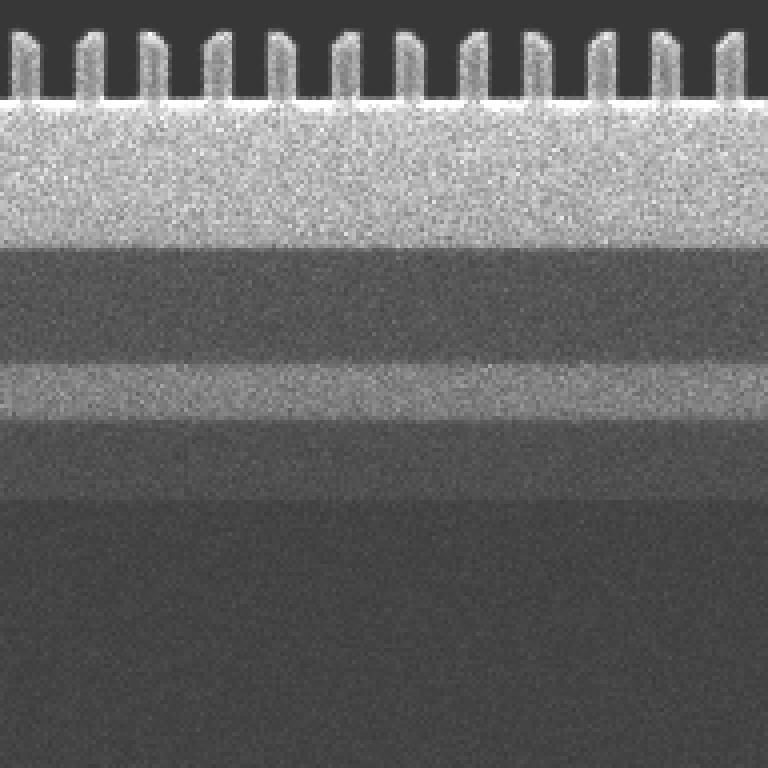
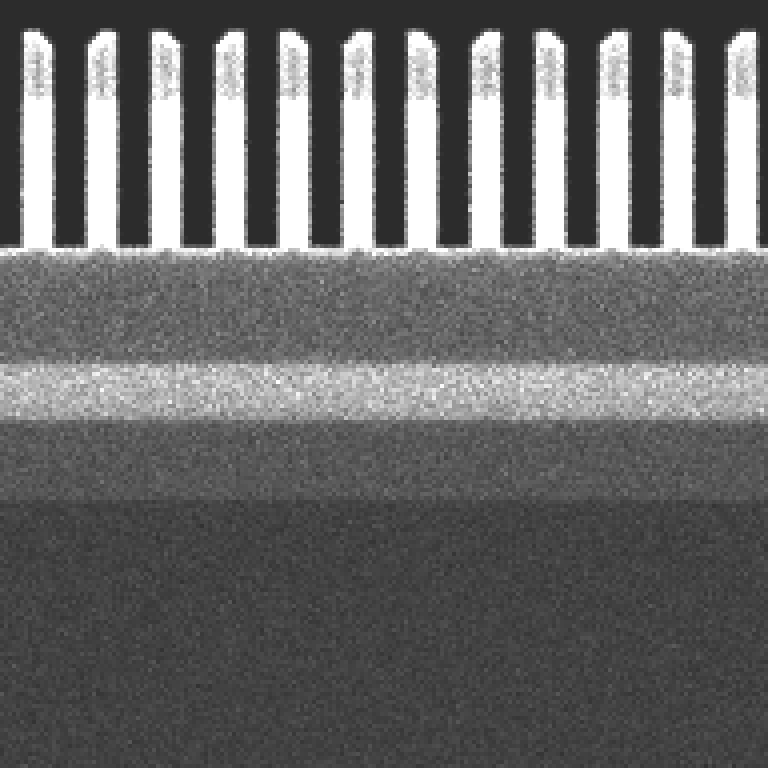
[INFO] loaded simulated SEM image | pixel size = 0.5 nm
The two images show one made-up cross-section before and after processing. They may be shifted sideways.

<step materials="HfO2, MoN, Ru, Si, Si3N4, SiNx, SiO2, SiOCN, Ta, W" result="removed HfO2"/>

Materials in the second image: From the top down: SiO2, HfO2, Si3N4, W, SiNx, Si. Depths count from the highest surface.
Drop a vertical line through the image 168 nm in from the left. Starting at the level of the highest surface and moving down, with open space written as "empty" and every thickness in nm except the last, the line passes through empty 108, Si3N4 58, W 28, SiNx 40, Si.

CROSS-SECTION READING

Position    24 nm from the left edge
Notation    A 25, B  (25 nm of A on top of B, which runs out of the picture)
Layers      empty 6, SiO2 28, HfO2 74, Si3N4 58, W 28, SiNx 40, Si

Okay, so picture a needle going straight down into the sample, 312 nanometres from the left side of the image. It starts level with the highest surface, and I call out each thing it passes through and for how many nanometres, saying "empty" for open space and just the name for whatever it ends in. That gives SiO2 34, HfO2 74, Si3N4 58, W 28, SiNx 40, Si